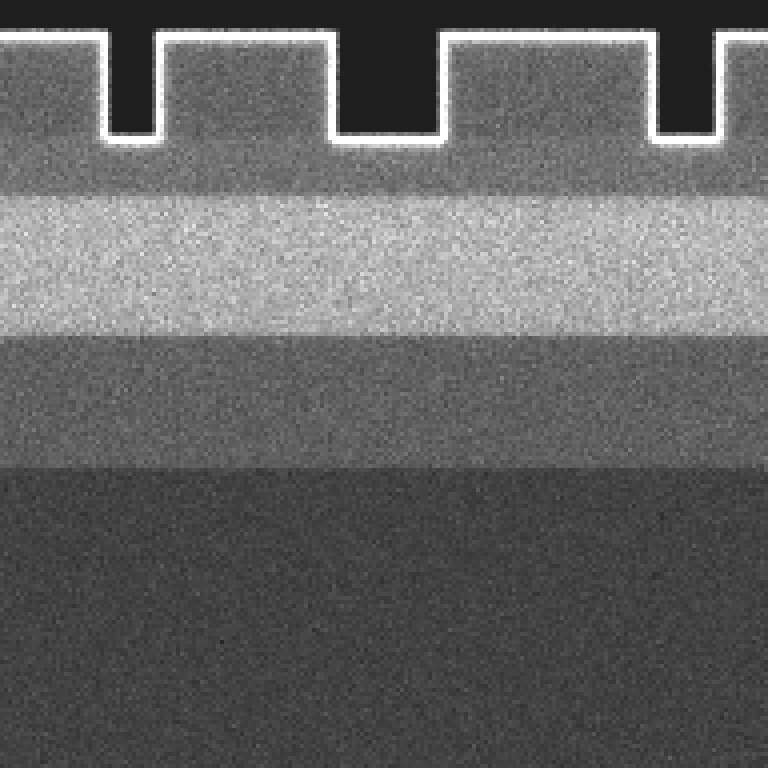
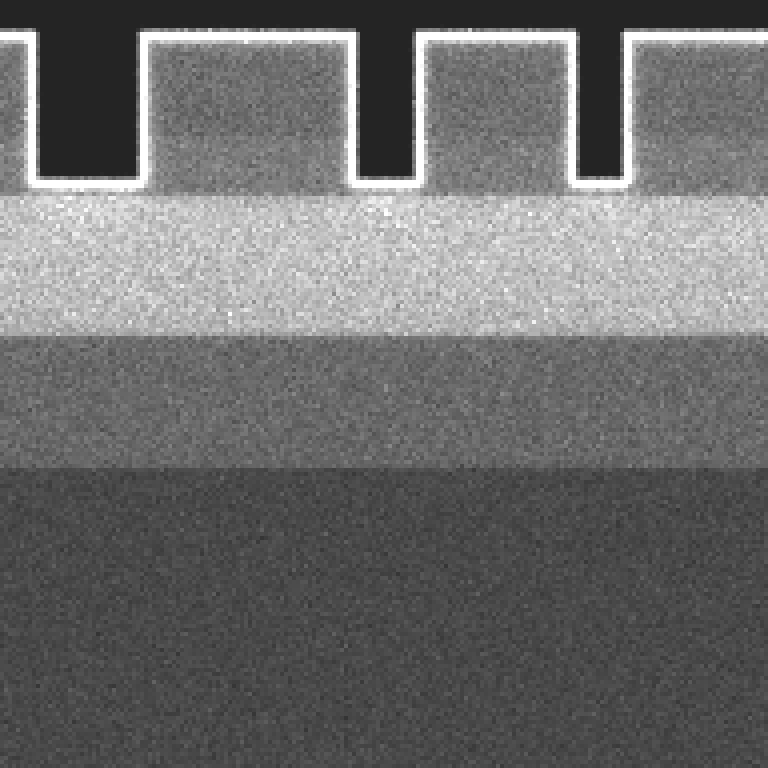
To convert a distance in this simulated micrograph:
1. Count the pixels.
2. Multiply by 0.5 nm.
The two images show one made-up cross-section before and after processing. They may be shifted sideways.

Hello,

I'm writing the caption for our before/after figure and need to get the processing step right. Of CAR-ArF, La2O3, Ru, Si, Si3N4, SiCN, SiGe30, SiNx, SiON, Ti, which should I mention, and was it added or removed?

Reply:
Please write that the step removed Si3N4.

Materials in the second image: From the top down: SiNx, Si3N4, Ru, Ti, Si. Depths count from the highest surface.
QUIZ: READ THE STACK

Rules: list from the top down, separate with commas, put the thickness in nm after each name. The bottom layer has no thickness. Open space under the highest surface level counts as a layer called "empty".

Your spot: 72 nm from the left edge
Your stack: SiNx 52, Si3N4 30, Ru 70, Ti 66, Si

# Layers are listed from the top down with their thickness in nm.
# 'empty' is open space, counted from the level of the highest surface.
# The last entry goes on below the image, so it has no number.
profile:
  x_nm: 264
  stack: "SiNx 52, Si3N4 30, Ru 70, Ti 66, Si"